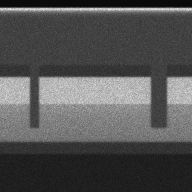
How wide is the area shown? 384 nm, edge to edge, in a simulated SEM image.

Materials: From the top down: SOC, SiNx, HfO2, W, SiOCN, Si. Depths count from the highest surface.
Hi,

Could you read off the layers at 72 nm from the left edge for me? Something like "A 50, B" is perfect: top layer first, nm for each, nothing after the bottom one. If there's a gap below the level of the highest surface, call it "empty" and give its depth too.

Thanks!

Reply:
SOC 240, W 28, SiOCN 24, Si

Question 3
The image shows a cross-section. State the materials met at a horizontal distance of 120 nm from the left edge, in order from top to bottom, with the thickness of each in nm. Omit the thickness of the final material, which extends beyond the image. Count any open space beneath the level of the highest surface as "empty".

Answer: SOC 114, SiNx 24, HfO2 54, W 76, SiOCN 24, Si